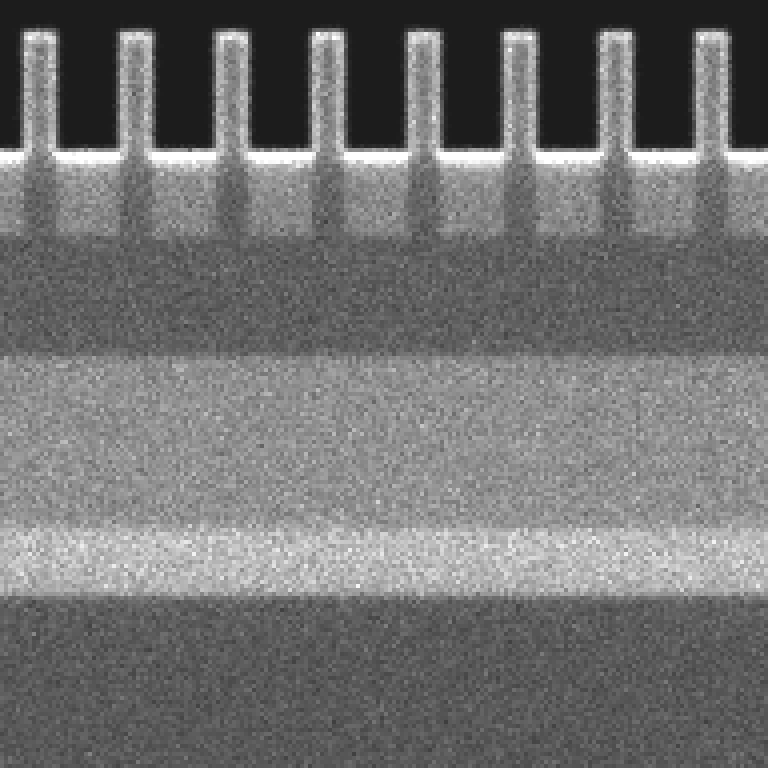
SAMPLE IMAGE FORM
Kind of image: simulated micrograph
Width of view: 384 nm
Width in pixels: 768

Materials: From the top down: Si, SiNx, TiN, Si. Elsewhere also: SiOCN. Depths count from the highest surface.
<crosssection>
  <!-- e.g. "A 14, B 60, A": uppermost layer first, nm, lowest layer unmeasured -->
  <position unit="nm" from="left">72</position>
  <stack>Si 162, SiNx 86, TiN 34, Si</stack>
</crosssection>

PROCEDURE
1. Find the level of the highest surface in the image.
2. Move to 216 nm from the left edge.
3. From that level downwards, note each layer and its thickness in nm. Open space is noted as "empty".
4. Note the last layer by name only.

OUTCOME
Si 162, SiNx 86, TiN 34, Si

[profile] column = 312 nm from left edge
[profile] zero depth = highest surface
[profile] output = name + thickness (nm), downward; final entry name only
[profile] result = Si 162, SiNx 86, TiN 34, Si